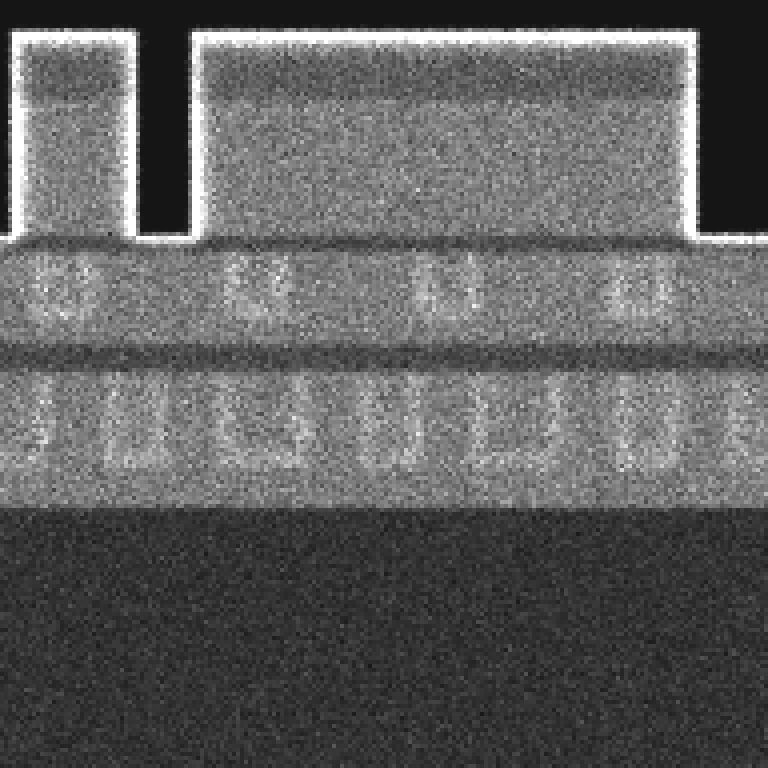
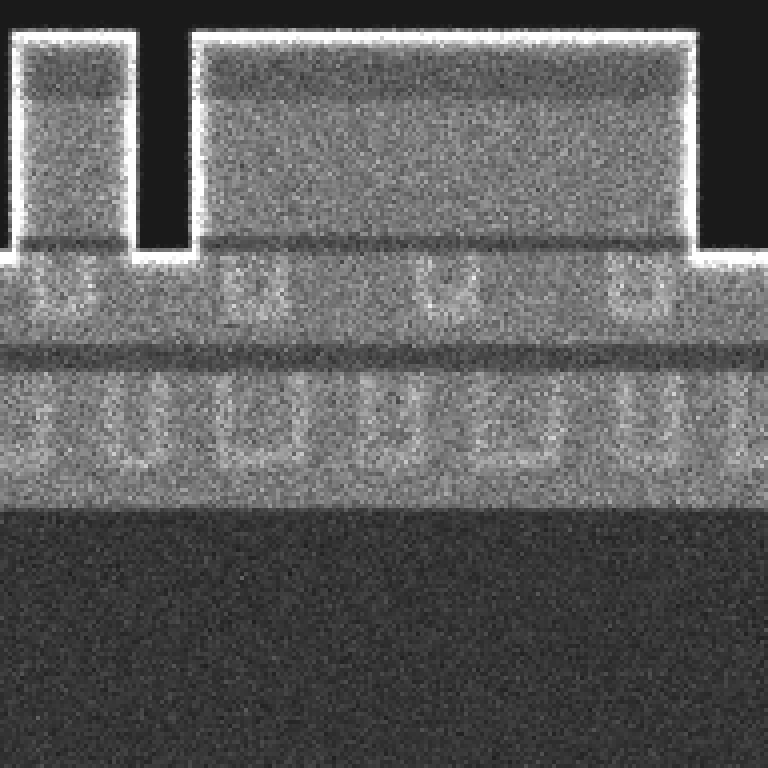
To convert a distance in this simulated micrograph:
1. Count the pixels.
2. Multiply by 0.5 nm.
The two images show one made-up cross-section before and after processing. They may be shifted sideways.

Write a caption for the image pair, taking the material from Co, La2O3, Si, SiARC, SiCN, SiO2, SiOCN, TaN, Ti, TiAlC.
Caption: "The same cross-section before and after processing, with SiCN removed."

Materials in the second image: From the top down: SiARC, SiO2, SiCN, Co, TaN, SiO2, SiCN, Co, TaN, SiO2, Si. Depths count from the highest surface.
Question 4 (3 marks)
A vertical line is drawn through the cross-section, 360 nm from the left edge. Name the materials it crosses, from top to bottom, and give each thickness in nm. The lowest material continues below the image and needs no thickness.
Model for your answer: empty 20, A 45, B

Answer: empty 110, SiO2 46, SiCN 14, SiO2 68, Si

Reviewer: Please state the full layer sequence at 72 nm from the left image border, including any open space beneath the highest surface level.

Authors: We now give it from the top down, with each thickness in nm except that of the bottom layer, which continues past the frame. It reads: empty 110, SiO2 46, SiCN 14, Co 40, TaN 8, SiO2 20, Si